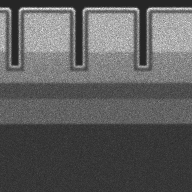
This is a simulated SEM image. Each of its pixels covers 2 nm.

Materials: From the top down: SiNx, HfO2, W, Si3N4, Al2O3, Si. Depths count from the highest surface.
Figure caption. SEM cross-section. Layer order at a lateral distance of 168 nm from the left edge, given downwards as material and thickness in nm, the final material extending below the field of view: empty 2, SiNx 124, W 24, Si3N4 32, Al2O3 50, Si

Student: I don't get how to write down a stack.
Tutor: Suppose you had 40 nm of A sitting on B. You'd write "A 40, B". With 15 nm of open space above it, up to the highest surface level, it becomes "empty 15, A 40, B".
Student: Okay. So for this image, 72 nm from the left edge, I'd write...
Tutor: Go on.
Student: SiNx 10, HfO2 78, W 62, Si3N4 32, Al2O3 50, Si